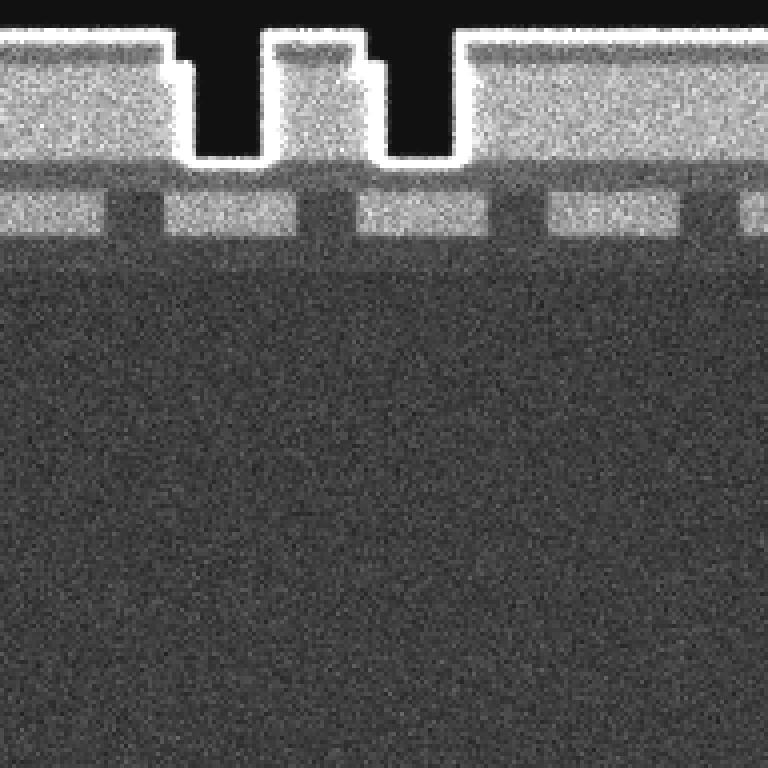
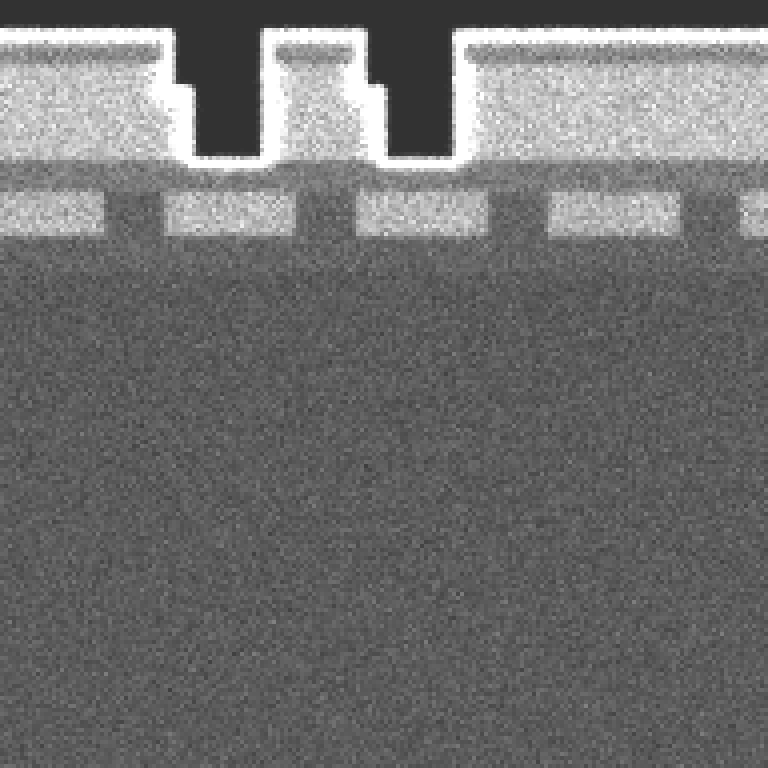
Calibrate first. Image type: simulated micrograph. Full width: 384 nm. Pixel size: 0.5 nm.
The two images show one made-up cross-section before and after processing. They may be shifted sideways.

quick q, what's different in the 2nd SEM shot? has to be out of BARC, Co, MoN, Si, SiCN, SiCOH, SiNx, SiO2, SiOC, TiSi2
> SiO2 removed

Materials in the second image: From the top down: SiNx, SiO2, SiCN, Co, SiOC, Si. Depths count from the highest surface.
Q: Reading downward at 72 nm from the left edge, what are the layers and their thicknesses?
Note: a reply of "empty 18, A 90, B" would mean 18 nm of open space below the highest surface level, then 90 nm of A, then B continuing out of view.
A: SiNx 16, SiO2 48, SiCN 16, SiOC 40, Si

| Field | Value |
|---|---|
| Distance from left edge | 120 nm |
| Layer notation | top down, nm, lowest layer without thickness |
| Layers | empty 64, SiCN 16, Co 22, SiOC 18, Si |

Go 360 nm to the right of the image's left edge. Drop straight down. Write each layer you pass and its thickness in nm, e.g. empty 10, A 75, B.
SiNx 16, SiO2 48, SiCN 16, SiOC 40, Si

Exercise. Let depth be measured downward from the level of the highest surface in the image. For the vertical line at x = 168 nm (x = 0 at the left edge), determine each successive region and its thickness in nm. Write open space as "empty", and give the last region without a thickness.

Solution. SiNx 16, SiO2 48, SiCN 16, SiOC 40, Si